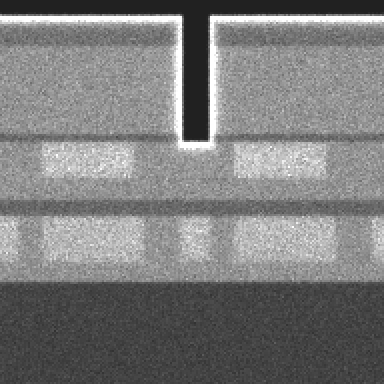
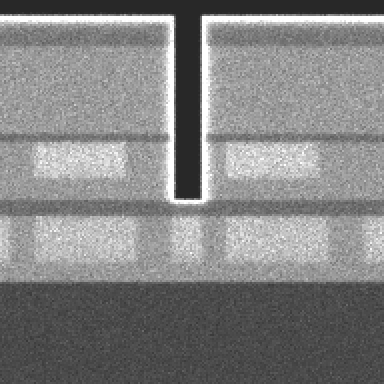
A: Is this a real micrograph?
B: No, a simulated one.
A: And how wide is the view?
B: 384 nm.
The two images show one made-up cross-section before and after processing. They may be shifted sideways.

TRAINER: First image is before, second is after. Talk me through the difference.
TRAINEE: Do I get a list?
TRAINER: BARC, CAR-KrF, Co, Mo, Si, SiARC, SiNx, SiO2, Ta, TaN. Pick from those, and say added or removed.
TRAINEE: removed: SiO2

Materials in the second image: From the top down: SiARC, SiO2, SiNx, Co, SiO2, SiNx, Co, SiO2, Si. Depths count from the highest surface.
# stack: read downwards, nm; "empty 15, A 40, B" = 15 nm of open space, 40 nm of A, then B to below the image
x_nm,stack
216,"SiARC 30, SiO2 88, SiNx 8, SiO2 58, SiNx 16, SiO2 66, Si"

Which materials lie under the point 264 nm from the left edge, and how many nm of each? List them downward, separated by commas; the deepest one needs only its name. SiARC 30, SiO2 88, SiNx 8, Co 36, SiO2 22, SiNx 16, Co 46, SiO2 20, Si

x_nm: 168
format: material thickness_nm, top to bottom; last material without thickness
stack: SiARC 30, SiO2 88, SiNx 8, SiO2 58, SiNx 16, SiO2 66, Si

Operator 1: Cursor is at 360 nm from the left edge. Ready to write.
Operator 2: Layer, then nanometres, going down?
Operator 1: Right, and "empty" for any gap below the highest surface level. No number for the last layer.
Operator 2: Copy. SiARC 30, SiO2 88, SiNx 8, SiO2 58, SiNx 16, SiO2 66, Si